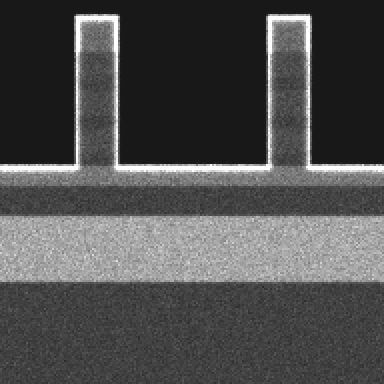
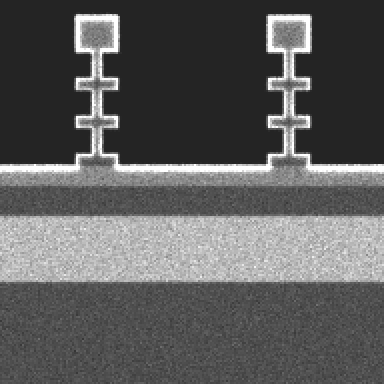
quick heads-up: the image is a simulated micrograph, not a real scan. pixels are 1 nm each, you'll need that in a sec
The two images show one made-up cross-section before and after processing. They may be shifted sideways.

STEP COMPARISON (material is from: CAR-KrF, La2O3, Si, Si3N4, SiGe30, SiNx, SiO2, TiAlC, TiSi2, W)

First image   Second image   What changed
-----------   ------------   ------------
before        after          SiGe30, removed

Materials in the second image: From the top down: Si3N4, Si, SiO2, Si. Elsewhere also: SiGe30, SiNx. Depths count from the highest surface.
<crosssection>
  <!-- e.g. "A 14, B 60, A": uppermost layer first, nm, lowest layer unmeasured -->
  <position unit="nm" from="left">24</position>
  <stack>empty 150, Si3N4 20, Si 30, SiO2 66, Si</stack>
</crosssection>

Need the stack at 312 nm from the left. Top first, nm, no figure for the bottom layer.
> empty 150, Si3N4 20, Si 30, SiO2 66, Si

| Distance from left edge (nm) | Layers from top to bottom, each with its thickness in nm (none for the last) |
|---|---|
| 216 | empty 150, Si3N4 20, Si 30, SiO2 66, Si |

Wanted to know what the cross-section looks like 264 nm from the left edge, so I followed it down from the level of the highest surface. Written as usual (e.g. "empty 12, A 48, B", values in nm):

empty 150, Si3N4 20, Si 30, SiO2 66, Si